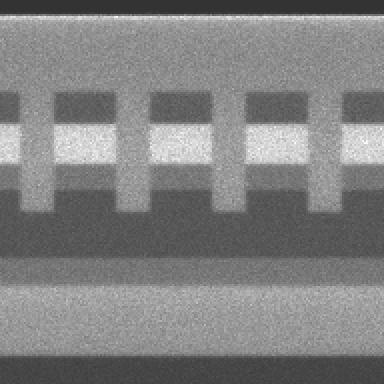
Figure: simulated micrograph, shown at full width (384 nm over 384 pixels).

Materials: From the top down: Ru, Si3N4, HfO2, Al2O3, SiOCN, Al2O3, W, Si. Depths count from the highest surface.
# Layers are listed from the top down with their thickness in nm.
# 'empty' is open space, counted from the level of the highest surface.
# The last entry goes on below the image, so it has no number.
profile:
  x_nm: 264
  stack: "Ru 76, Si3N4 32, HfO2 40, Al2O3 26, SiOCN 68, Al2O3 28, W 70, Si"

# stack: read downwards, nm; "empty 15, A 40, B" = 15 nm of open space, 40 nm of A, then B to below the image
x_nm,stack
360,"Ru 76, Si3N4 32, HfO2 40, Al2O3 26, SiOCN 68, Al2O3 28, W 70, Si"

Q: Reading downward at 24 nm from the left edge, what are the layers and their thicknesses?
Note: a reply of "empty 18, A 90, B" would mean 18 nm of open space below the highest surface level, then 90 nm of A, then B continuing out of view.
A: Ru 196, SiOCN 46, Al2O3 28, W 70, Si